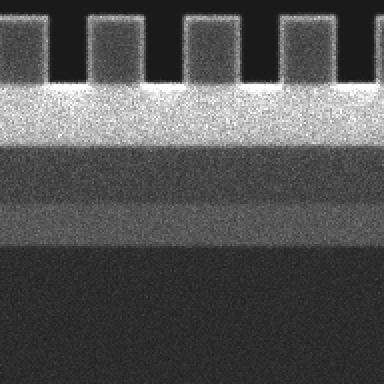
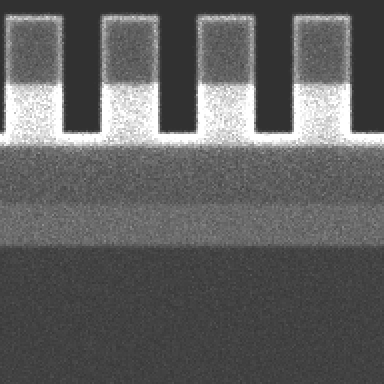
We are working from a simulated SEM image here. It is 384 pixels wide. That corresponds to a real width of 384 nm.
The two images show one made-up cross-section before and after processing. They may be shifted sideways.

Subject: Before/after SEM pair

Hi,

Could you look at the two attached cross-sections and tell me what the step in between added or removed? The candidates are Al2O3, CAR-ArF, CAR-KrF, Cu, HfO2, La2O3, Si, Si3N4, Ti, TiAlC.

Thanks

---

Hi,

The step removed HfO2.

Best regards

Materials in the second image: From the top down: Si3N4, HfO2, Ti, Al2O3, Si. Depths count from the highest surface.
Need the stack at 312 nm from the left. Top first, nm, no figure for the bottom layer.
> Si3N4 68, HfO2 62, Ti 58, Al2O3 42, Si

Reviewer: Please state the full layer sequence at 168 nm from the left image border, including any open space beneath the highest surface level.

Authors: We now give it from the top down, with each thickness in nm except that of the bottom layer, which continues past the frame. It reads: empty 118, HfO2 12, Ti 58, Al2O3 42, Si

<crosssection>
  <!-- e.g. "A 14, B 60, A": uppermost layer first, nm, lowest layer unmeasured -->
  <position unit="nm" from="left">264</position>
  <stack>empty 118, HfO2 12, Ti 58, Al2O3 42, Si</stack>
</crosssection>